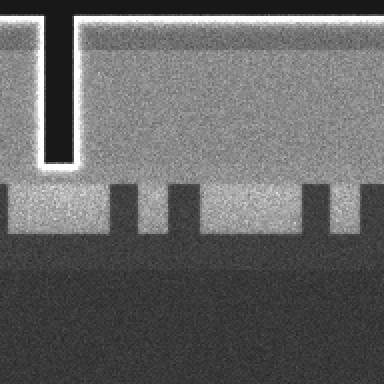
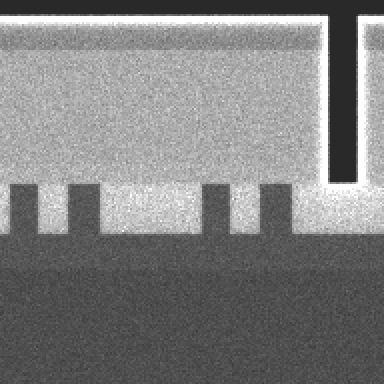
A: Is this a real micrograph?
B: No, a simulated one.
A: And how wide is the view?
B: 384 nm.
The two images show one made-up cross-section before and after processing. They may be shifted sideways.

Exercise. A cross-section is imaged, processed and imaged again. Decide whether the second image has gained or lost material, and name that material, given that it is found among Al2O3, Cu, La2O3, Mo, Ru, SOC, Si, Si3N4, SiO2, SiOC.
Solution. removed: Al2O3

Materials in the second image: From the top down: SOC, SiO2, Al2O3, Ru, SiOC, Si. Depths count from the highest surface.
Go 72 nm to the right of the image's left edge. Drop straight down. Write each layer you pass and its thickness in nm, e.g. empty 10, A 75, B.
SOC 34, SiO2 114, Al2O3 20, SiOC 86, Si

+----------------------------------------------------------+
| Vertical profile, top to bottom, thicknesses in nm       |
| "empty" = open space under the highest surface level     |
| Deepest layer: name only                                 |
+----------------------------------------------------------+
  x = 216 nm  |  SOC 34, SiO2 114, Al2O3 20, SiOC 86, Si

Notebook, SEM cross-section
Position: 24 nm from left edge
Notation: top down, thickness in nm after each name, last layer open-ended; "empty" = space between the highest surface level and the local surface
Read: SOC 34, SiO2 114, Al2O3 20, SiOC 86, Si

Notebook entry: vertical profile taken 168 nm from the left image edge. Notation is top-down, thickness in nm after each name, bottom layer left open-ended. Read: SOC 34, SiO2 114, Al2O3 20, Ru 50, SiOC 36, Si